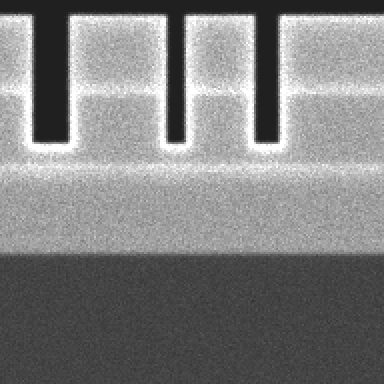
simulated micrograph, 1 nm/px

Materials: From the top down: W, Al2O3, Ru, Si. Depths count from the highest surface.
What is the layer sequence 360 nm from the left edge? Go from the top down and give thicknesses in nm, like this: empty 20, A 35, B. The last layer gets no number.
W 78, Al2O3 70, Ru 90, Si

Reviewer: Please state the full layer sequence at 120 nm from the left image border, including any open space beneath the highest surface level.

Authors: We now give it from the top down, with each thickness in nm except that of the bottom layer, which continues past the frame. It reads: W 78, Al2O3 70, Ru 90, Si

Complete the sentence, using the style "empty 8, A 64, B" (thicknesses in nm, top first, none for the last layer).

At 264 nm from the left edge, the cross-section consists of empty 128, Al2O3 20, Ru 90, Si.